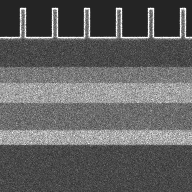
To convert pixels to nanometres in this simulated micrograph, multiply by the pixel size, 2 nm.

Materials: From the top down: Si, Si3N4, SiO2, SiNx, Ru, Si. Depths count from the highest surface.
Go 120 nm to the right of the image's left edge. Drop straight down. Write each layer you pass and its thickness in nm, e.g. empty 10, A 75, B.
empty 58, Si 60, Si3N4 32, SiO2 40, SiNx 54, Ru 30, Si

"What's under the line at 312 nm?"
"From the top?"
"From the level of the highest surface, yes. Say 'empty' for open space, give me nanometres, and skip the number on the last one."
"empty 58, Si 60, Si3N4 32, SiO2 40, SiNx 54, Ru 30, Si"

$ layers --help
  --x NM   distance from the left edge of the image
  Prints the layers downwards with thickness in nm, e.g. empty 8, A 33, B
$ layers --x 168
Si 118, Si3N4 32, SiO2 40, SiNx 54, Ru 30, Si